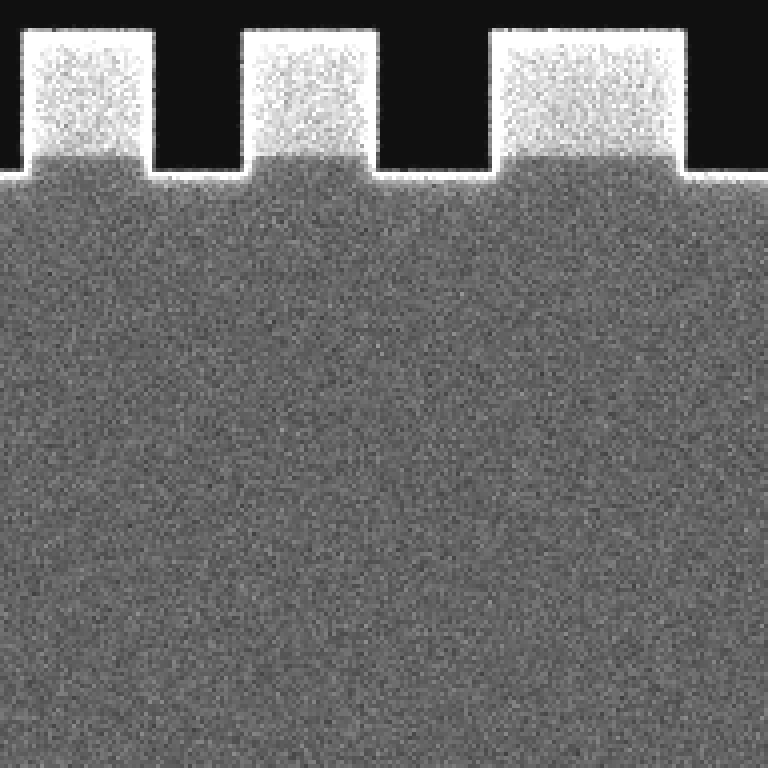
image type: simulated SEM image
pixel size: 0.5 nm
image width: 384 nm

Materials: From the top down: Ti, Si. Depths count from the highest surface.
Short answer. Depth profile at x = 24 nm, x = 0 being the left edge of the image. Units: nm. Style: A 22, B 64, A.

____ Ti 62, Si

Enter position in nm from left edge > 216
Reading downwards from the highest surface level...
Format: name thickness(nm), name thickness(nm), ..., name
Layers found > empty 70, Si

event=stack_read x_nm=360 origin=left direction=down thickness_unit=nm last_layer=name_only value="empty 70, Si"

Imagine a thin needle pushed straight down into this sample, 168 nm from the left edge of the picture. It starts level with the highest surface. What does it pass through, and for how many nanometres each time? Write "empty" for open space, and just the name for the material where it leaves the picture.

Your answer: Ti 62, Si